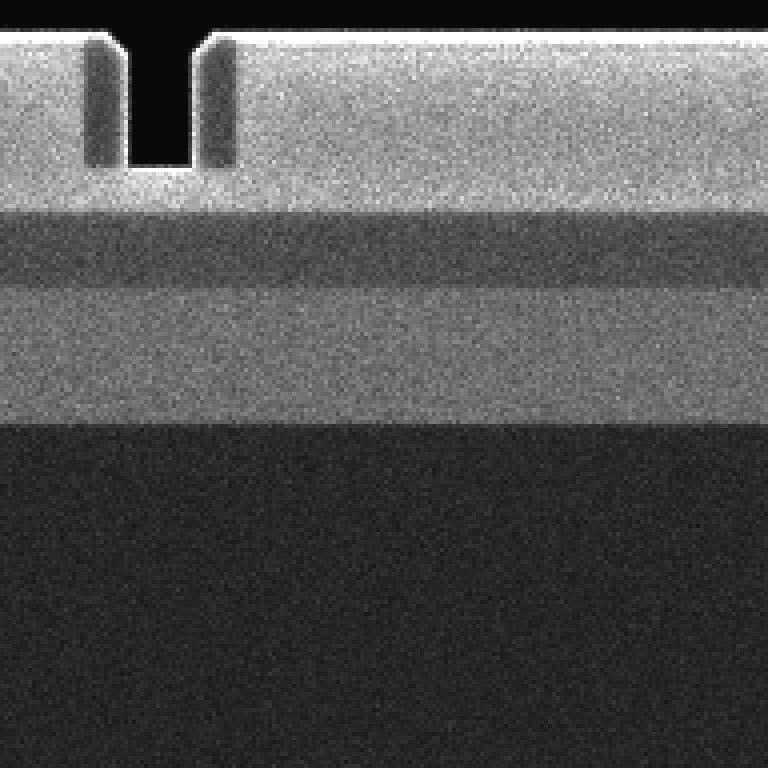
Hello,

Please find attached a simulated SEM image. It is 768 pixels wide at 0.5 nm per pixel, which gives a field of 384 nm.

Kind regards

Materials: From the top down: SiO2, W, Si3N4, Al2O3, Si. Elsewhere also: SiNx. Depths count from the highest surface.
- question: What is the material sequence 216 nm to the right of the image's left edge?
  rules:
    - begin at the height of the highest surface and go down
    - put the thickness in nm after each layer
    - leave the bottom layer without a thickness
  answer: SiO2 10, W 80, Si3N4 38, Al2O3 68, Si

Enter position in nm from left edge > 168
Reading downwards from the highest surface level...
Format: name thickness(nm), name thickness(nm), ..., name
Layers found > SiO2 10, W 80, Si3N4 38, Al2O3 68, Si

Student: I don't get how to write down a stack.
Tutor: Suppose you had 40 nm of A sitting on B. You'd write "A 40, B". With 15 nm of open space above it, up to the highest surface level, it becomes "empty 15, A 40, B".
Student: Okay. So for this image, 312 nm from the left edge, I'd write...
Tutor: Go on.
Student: SiO2 10, W 80, Si3N4 38, Al2O3 68, Si